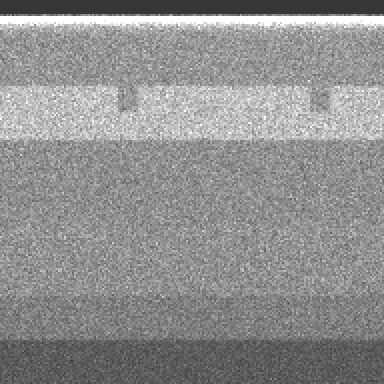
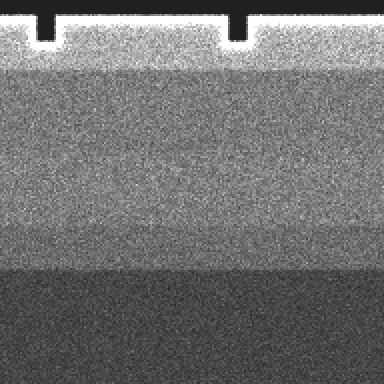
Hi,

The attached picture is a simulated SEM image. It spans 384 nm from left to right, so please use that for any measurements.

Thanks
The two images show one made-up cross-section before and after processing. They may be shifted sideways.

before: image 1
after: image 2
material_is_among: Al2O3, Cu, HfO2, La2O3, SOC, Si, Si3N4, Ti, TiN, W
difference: SOC, removed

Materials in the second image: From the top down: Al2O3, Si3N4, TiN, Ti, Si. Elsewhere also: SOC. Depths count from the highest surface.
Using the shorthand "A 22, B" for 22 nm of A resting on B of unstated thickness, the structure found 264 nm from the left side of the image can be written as Al2O3 54, Si3N4 82, TiN 74, Ti 44, Si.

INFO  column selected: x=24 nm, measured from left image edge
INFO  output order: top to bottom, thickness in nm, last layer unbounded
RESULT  Al2O3 54, Si3N4 82, TiN 74, Ti 44, Si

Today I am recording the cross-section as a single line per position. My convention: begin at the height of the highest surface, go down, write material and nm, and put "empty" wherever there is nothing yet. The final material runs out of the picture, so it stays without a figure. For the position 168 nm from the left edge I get Al2O3 54, Si3N4 82, TiN 74, Ti 44, Si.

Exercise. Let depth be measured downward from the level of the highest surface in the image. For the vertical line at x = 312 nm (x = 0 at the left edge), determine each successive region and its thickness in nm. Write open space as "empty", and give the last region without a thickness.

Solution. Al2O3 54, Si3N4 82, TiN 74, Ti 44, Si